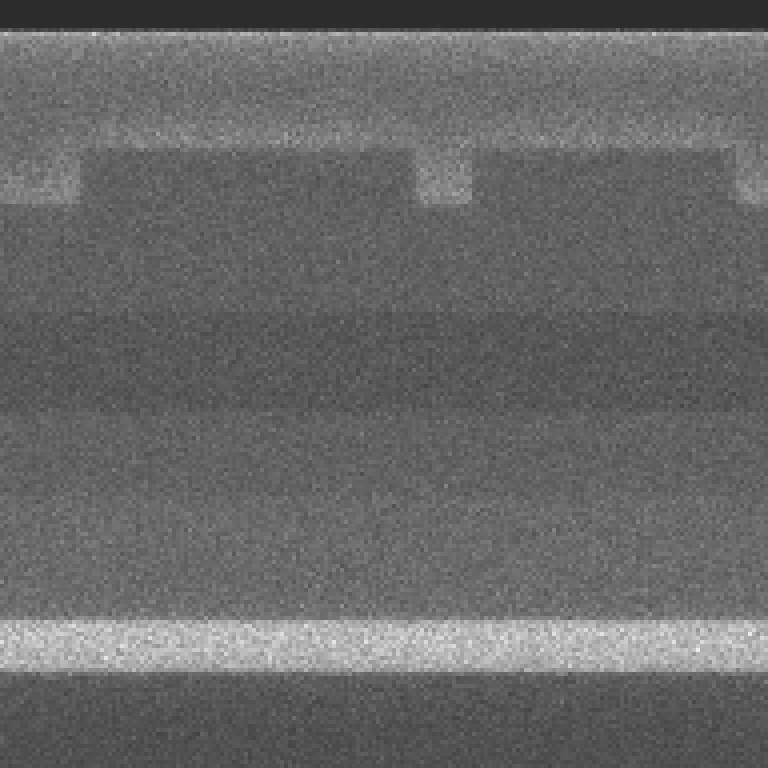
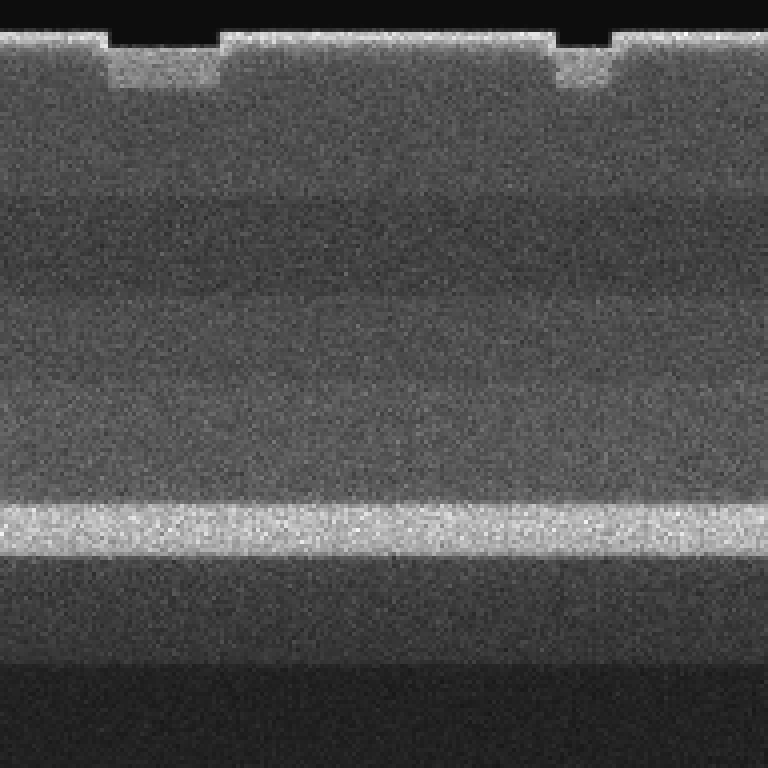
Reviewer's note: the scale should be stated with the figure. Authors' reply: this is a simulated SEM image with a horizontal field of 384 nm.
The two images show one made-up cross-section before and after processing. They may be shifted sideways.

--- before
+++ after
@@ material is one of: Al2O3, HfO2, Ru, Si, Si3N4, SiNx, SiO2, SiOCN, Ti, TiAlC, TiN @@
Ru removed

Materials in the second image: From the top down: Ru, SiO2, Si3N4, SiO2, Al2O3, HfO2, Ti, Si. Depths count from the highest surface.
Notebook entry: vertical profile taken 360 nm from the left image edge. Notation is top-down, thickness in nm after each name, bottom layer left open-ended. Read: SiO2 82, Si3N4 50, SiO2 42, Al2O3 62, HfO2 26, Ti 54, Si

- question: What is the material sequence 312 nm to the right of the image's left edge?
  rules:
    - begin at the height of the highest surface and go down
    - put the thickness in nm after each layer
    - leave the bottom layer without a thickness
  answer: SiO2 82, Si3N4 50, SiO2 42, Al2O3 62, HfO2 26, Ti 54, Si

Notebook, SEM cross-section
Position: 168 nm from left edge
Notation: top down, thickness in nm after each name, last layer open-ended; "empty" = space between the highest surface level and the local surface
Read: SiO2 82, Si3N4 50, SiO2 42, Al2O3 62, HfO2 26, Ti 54, Si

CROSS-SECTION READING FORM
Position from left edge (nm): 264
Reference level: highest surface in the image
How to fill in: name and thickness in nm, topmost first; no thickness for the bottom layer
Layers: SiO2 82, Si3N4 50, SiO2 42, Al2O3 62, HfO2 26, Ti 54, Si